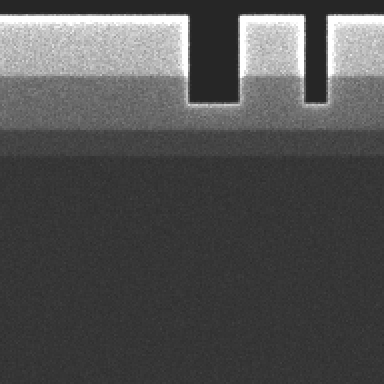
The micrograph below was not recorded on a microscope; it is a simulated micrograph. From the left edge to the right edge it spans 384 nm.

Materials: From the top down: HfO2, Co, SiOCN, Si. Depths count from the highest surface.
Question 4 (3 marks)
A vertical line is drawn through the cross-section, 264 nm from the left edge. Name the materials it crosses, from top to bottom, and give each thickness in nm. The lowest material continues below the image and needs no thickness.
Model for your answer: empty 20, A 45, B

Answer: HfO2 60, Co 54, SiOCN 26, Si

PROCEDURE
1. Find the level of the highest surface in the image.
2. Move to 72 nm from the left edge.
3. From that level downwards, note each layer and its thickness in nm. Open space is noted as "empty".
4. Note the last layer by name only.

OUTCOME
HfO2 60, Co 54, SiOCN 26, Si